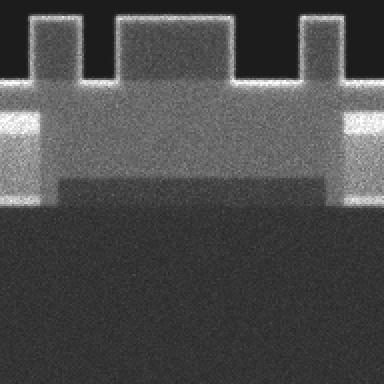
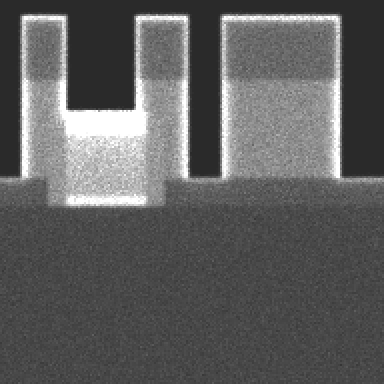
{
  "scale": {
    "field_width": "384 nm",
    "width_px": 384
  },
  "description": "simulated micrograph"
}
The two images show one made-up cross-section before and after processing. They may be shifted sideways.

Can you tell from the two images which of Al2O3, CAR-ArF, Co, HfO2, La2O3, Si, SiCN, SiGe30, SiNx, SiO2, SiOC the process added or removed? Yes, it removed SiO2.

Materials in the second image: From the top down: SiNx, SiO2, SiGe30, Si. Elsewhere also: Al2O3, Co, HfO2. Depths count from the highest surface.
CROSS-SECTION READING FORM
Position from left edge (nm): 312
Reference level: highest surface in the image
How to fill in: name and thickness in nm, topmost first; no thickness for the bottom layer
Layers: SiNx 64, SiO2 98, SiGe30 28, Si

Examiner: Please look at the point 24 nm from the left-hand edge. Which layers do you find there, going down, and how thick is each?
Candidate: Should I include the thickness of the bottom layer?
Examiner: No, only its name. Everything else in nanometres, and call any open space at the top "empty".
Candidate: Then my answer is SiNx 64, SiO2 98, SiGe30 28, Si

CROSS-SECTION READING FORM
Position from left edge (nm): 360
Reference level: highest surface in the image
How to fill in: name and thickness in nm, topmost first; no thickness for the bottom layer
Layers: empty 162, SiGe30 28, Si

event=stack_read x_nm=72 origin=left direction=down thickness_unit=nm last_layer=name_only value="empty 96, HfO2 22, Co 62, HfO2 10, Si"